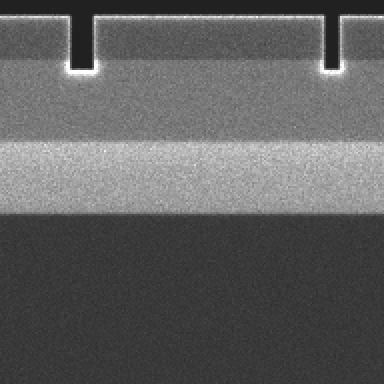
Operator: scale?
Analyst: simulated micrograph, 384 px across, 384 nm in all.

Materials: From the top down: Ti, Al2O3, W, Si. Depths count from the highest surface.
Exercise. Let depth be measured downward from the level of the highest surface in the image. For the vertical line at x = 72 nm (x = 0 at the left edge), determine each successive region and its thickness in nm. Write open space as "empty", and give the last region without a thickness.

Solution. empty 54, Al2O3 72, W 72, Si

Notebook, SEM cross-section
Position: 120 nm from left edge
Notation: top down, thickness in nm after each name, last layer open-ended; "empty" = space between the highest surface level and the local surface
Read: Ti 44, Al2O3 82, W 72, Si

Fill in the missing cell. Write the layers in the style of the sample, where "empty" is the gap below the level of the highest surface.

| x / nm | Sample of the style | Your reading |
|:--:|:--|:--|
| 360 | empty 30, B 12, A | Ti 44, Al2O3 82, W 72, Si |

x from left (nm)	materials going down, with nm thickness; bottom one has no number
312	Ti 44, Al2O3 82, W 72, Si